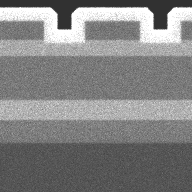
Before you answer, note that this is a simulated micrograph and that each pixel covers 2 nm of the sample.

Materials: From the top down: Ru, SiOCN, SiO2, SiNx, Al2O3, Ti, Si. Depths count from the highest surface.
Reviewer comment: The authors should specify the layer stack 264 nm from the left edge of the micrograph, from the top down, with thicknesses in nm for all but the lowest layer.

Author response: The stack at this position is Ru 26, SiOCN 38, SiO2 32, SiNx 88, Al2O3 40, Ti 46, Si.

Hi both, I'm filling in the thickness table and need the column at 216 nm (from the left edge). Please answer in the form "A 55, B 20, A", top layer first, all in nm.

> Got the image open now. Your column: Ru 26, SiOCN 38, SiO2 32, SiNx 88, Al2O3 40, Ti 46, Si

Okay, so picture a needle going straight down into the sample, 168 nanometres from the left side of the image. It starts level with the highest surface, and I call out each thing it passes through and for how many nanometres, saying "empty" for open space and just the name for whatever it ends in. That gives Ru 70, SiO2 26, SiNx 88, Al2O3 40, Ti 46, Si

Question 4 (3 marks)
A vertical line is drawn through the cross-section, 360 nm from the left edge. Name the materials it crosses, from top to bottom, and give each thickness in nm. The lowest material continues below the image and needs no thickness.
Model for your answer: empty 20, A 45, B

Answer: Ru 70, SiO2 26, SiNx 88, Al2O3 40, Ti 46, Si